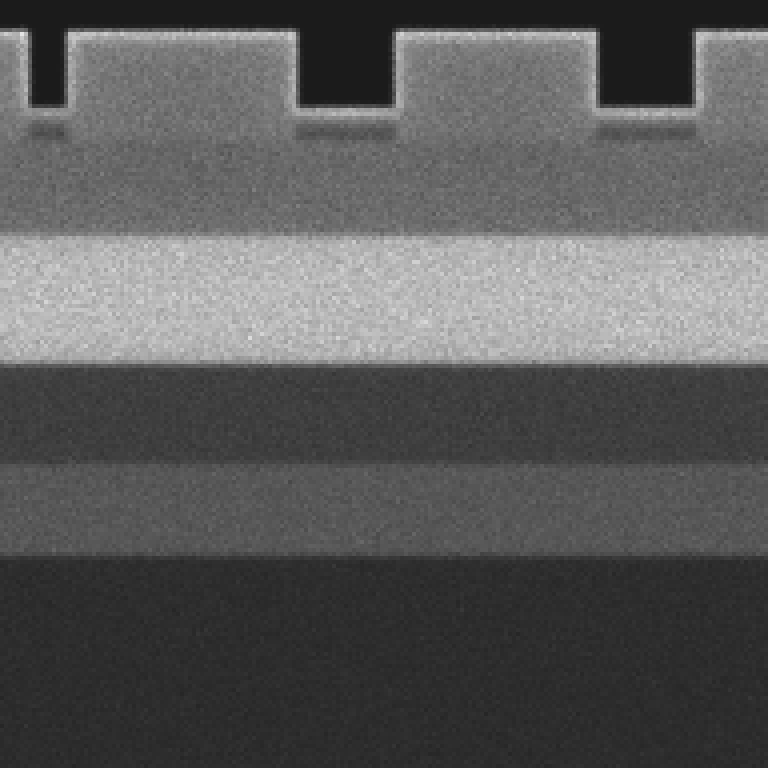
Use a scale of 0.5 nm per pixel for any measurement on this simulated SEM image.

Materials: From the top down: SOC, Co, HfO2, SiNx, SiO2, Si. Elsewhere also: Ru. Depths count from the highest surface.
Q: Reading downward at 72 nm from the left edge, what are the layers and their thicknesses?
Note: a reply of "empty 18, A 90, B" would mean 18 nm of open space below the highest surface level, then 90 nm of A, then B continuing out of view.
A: Ru 54, Co 48, HfO2 64, SiNx 50, SiO2 46, Si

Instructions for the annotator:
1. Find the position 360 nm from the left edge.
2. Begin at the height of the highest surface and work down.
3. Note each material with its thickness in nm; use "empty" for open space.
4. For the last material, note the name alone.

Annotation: Ru 54, Co 48, HfO2 64, SiNx 50, SiO2 46, Si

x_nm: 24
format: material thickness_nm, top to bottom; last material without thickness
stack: empty 38, SOC 16, Co 48, HfO2 64, SiNx 50, SiO2 46, Si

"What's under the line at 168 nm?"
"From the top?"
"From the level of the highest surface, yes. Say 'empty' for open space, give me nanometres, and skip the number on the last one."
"empty 38, SOC 16, Co 48, HfO2 64, SiNx 50, SiO2 46, Si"